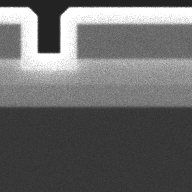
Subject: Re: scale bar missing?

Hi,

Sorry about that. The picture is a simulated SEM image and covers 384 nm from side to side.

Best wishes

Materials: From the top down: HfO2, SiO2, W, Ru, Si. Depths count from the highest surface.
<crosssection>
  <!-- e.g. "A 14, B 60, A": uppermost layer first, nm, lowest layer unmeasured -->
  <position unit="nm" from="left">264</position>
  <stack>HfO2 32, SiO2 70, W 52, Ru 44, Si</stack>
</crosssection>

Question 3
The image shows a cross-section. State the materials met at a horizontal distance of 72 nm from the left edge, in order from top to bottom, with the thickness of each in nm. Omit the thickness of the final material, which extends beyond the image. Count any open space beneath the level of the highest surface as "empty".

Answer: empty 16, HfO2 108, W 30, Ru 44, Si